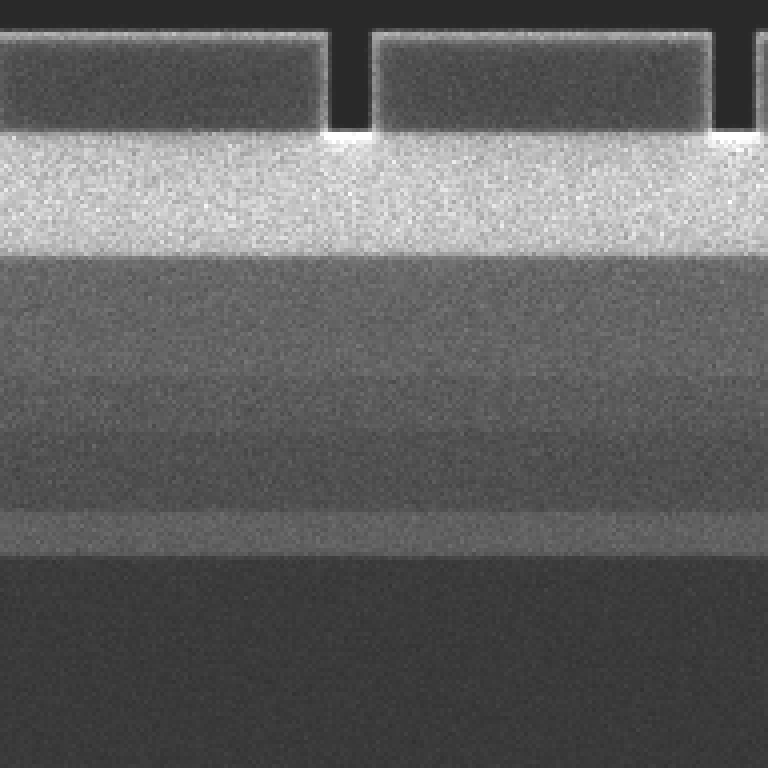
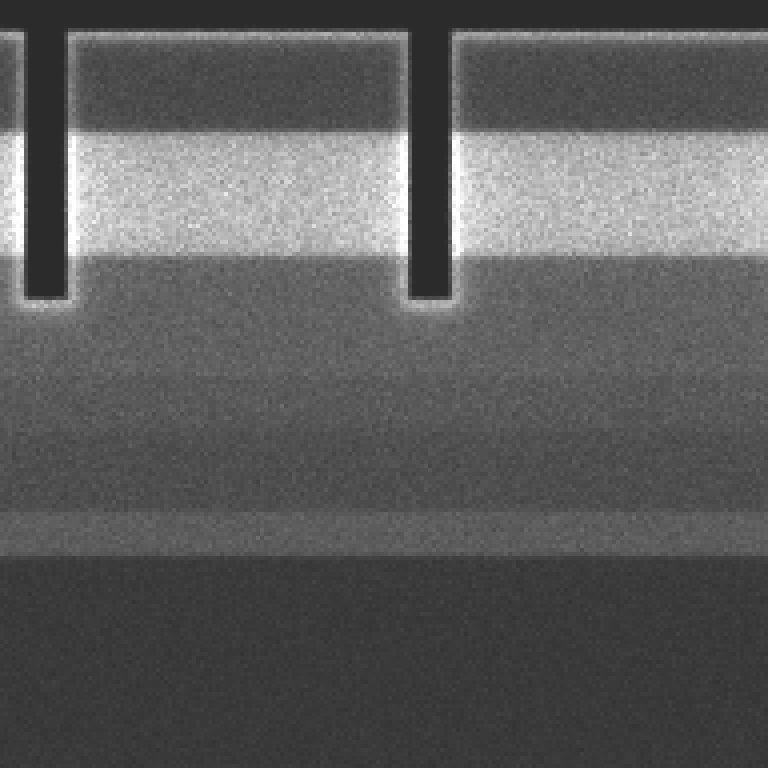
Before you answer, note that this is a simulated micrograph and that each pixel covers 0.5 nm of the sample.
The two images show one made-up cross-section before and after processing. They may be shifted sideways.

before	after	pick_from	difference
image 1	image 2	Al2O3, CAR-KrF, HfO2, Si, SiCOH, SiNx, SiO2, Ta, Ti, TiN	Al2O3 and HfO2 removed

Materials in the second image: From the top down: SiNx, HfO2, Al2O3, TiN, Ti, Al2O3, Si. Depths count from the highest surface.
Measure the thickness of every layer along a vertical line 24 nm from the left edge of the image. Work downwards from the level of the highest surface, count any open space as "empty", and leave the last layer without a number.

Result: empty 134, Al2O3 38, TiN 28, Ti 40, Al2O3 22, Si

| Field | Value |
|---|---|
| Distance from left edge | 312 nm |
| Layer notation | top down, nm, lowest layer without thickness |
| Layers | SiNx 50, HfO2 62, Al2O3 60, TiN 28, Ti 40, Al2O3 22, Si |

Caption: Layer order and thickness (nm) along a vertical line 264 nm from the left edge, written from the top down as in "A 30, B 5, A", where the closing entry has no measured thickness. SiNx 50, HfO2 62, Al2O3 60, TiN 28, Ti 40, Al2O3 22, Si